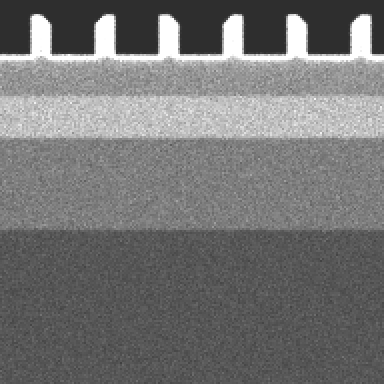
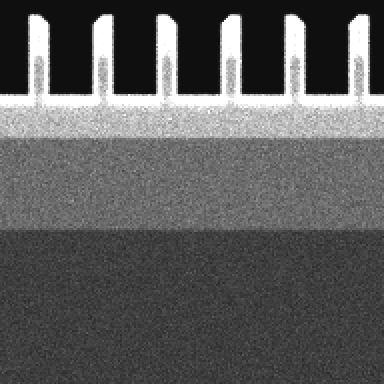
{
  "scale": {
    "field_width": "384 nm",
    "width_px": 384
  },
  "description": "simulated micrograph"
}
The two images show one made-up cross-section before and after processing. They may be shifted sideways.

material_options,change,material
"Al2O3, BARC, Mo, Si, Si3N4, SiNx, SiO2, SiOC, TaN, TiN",removed,TiN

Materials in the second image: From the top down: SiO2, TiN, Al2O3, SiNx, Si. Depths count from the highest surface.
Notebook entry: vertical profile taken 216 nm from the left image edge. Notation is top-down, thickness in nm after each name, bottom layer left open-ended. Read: empty 80, Al2O3 42, SiNx 92, Si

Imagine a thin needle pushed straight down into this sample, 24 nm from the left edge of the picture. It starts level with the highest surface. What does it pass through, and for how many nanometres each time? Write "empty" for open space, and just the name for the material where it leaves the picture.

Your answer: empty 80, Al2O3 42, SiNx 92, Si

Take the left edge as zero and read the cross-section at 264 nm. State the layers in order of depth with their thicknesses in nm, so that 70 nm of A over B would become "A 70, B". empty 80, Al2O3 42, SiNx 92, Si